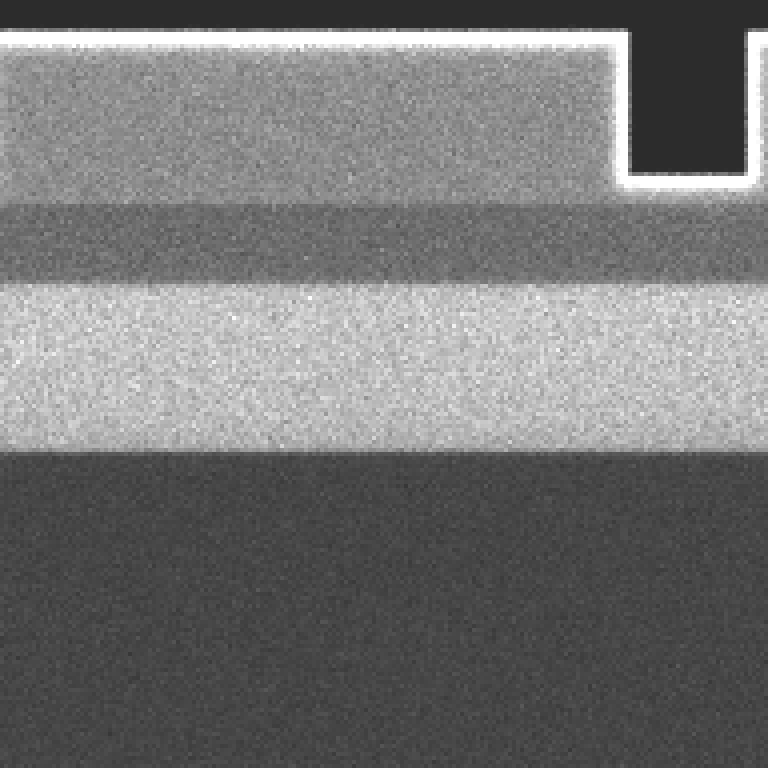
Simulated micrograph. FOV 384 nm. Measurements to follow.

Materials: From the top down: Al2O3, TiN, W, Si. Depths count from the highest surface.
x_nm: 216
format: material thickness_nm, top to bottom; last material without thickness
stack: Al2O3 86, TiN 40, W 84, Si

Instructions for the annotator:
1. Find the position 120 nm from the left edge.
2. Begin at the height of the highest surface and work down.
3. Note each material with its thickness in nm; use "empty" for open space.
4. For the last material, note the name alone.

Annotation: Al2O3 86, TiN 40, W 84, Si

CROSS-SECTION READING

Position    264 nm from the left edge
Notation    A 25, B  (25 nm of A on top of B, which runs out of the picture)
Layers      Al2O3 86, TiN 40, W 84, Si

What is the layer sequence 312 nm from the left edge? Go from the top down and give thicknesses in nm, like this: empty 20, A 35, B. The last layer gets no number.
Al2O3 86, TiN 40, W 84, Si